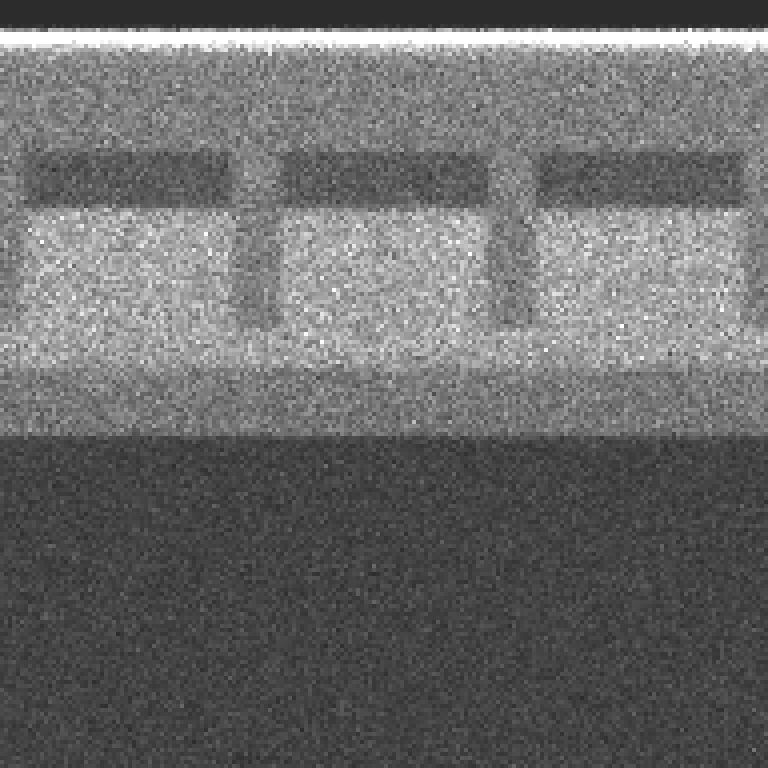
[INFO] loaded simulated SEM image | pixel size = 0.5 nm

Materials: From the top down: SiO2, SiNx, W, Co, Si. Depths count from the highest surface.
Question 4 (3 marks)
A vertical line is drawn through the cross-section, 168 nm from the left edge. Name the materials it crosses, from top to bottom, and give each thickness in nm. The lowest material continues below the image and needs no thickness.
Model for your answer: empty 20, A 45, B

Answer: SiO2 60, SiNx 28, W 80, Co 34, Si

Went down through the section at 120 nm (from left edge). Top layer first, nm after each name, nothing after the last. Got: SiO2 148, W 20, Co 34, Si